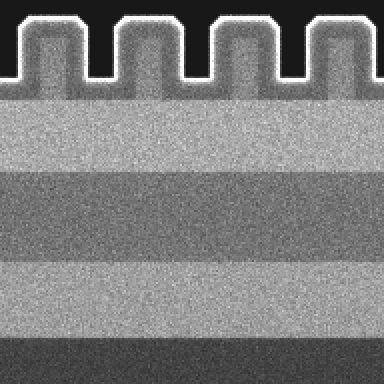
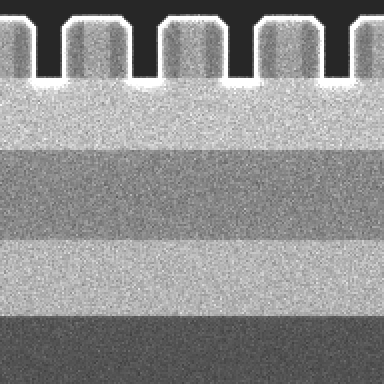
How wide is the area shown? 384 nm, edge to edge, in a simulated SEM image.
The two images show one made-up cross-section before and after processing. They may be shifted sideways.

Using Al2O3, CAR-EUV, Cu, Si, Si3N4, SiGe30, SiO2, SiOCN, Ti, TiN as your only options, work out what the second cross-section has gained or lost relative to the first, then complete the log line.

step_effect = removed SiOCN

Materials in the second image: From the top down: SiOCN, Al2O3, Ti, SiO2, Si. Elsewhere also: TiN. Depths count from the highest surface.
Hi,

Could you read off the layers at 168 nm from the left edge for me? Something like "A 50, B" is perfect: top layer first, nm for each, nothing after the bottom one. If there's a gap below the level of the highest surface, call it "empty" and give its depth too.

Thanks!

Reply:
SiOCN 62, Al2O3 72, Ti 90, SiO2 76, Si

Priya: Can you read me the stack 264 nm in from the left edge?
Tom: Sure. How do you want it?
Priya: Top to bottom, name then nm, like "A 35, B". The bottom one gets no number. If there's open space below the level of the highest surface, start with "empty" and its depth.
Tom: SiOCN 62, Al2O3 72, Ti 90, SiO2 76, Si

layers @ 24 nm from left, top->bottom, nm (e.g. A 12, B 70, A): SiOCN 62, Al2O3 72, Ti 90, SiO2 76, Si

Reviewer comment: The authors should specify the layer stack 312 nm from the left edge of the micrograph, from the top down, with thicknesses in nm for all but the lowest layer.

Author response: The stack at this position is SiOCN 62, Al2O3 72, Ti 90, SiO2 76, Si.